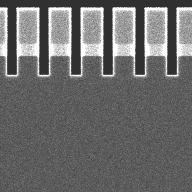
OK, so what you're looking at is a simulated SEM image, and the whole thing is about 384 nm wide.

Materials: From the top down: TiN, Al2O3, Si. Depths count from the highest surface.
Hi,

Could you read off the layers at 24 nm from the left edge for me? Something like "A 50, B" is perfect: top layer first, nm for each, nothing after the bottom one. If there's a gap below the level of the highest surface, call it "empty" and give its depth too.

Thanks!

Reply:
empty 134, Si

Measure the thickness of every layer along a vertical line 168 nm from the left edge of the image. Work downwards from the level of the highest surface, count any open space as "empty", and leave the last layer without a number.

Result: TiN 72, Al2O3 24, Si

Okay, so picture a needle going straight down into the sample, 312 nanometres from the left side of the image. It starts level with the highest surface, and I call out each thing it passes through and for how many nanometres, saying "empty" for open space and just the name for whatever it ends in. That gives TiN 72, Al2O3 24, Si